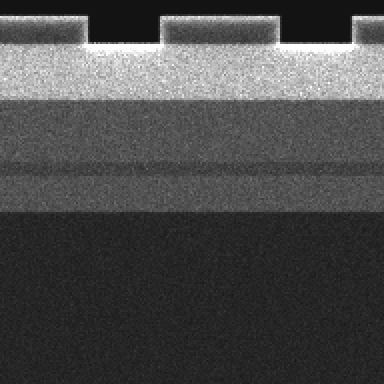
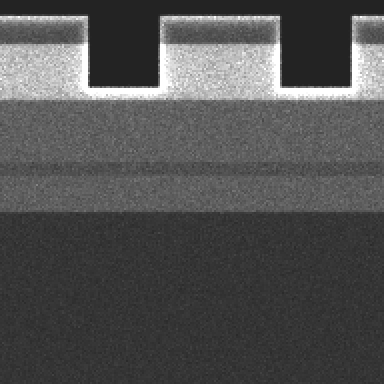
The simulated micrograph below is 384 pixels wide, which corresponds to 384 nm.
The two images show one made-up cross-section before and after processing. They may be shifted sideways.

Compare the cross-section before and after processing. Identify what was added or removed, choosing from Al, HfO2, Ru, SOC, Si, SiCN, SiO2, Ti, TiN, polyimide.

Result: HfO2 removed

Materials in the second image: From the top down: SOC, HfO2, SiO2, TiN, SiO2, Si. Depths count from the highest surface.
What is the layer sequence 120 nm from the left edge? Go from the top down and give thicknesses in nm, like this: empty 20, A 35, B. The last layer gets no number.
empty 72, HfO2 12, SiO2 62, TiN 14, SiO2 36, Si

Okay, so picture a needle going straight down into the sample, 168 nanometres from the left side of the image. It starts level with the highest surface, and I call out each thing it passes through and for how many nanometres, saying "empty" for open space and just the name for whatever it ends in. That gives SOC 28, HfO2 56, SiO2 62, TiN 14, SiO2 36, Si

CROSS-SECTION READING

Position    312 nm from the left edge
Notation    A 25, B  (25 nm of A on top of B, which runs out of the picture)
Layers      empty 72, HfO2 12, SiO2 62, TiN 14, SiO2 36, Si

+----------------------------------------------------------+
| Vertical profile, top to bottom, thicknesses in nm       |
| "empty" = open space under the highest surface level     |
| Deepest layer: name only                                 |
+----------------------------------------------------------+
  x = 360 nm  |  SOC 28, HfO2 56, SiO2 62, TiN 14, SiO2 36, Si